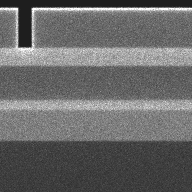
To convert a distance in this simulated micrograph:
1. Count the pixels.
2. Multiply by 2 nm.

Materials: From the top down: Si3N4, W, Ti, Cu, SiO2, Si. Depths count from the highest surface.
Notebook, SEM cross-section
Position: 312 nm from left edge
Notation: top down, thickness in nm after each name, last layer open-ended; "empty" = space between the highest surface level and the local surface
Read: Si3N4 80, W 36, Ti 68, Cu 20, SiO2 62, Si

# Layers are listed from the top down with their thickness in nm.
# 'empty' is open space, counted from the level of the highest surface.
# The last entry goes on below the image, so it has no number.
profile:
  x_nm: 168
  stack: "Si3N4 80, W 36, Ti 68, Cu 20, SiO2 62, Si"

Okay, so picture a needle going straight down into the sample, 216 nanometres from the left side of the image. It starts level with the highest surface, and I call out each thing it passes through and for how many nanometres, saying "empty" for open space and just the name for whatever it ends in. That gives Si3N4 80, W 36, Ti 68, Cu 20, SiO2 62, Si